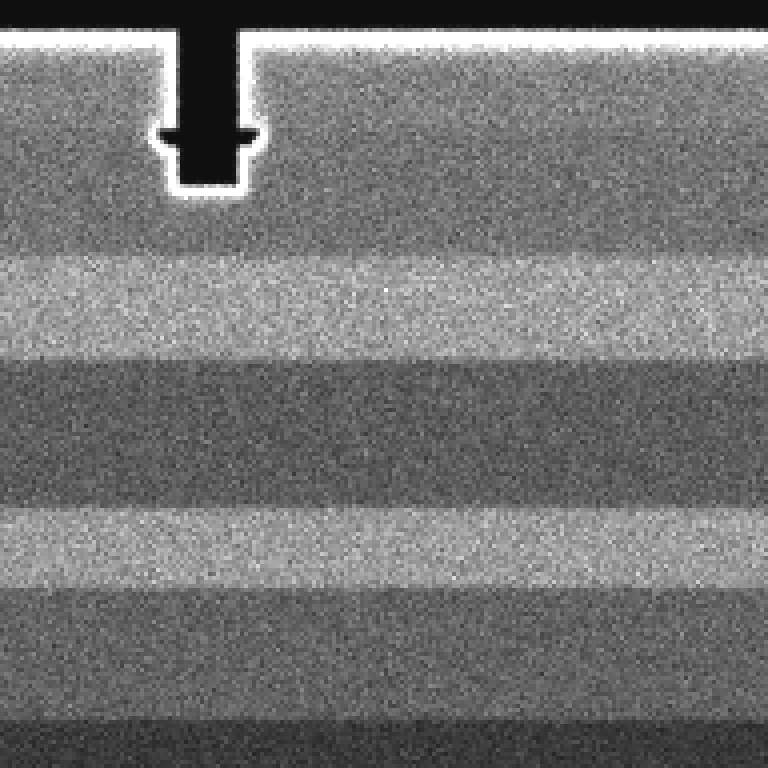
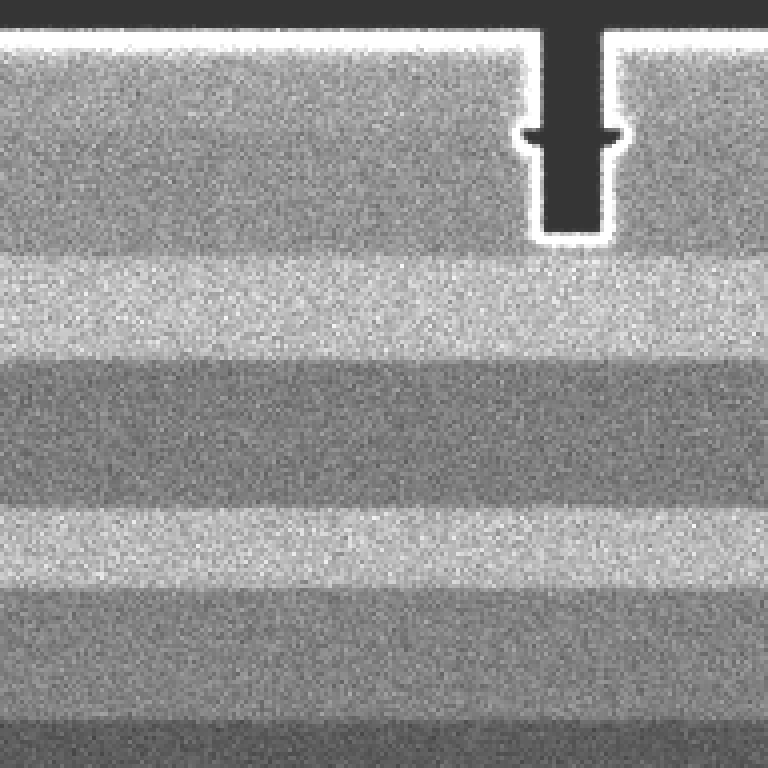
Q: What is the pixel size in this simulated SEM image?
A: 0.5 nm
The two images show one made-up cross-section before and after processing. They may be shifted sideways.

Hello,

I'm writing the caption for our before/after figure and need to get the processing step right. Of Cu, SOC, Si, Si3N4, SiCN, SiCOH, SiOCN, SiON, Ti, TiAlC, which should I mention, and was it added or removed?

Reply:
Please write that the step removed Si3N4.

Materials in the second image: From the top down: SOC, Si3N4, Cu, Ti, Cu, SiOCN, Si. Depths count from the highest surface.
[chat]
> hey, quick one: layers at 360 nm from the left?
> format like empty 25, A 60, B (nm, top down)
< SOC 48, Si3N4 64, Cu 52, Ti 74, Cu 40, SiOCN 66, Si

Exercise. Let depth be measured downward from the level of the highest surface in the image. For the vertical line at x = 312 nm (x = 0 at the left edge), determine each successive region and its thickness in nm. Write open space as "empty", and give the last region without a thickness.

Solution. SOC 48, Si3N4 64, Cu 52, Ti 74, Cu 40, SiOCN 66, Si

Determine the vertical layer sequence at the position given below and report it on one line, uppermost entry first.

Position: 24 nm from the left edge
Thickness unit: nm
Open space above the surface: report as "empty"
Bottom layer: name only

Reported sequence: SOC 48, Si3N4 64, Cu 52, Ti 74, Cu 40, SiOCN 66, Si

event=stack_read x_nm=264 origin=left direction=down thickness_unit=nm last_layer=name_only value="SOC 48, empty 10, Si3N4 54, Cu 52, Ti 74, Cu 40, SiOCN 66, Si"